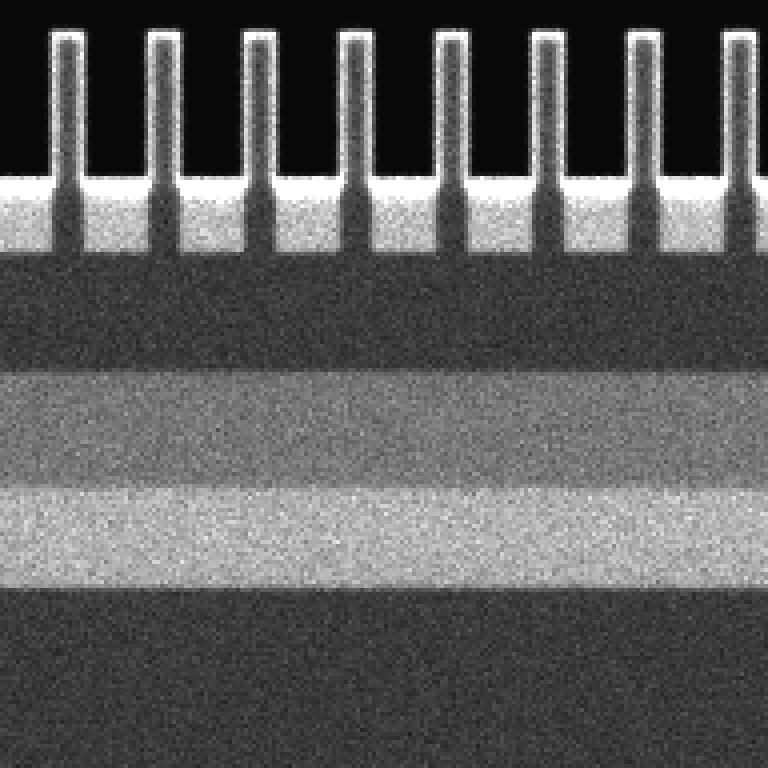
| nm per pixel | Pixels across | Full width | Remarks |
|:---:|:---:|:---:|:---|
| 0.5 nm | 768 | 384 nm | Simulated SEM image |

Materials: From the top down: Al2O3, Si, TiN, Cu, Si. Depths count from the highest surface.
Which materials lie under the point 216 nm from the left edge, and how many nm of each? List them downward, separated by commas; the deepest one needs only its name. empty 74, Al2O3 36, Si 60, TiN 58, Cu 50, Si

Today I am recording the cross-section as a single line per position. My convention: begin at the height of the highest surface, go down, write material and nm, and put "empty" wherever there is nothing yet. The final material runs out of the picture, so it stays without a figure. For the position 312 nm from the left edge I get empty 74, Al2O3 36, Si 60, TiN 58, Cu 50, Si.